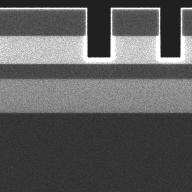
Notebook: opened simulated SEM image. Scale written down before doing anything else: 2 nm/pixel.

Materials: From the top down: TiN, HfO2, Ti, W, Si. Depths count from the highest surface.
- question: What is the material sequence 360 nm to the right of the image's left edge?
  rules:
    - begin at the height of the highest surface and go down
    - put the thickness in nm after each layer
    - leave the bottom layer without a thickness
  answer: empty 100, HfO2 12, Ti 30, W 68, Si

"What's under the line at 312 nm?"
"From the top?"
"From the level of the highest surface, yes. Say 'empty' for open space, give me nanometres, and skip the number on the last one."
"TiN 56, HfO2 56, Ti 30, W 68, Si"